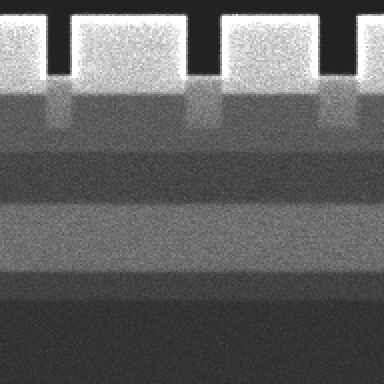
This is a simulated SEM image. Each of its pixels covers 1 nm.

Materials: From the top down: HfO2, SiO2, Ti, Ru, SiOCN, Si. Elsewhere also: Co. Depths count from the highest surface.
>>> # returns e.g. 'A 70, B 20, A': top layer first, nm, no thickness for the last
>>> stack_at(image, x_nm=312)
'HfO2 78, SiO2 58, Ti 52, Ru 68, SiOCN 28, Si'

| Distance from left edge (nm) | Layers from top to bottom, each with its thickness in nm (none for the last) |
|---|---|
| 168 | HfO2 78, SiO2 58, Ti 52, Ru 68, SiOCN 28, Si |